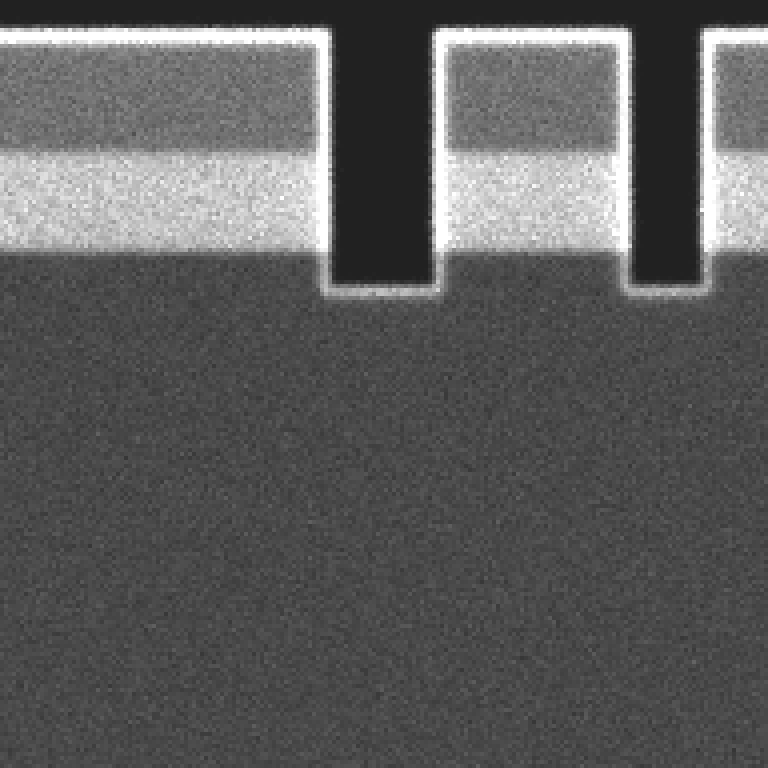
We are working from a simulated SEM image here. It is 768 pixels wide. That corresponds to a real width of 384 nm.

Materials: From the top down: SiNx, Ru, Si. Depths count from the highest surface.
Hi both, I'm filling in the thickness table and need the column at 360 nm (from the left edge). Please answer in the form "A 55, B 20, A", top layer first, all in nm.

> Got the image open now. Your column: SiNx 60, Ru 50, Si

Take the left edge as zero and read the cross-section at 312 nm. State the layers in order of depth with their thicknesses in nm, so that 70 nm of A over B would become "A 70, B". SiNx 60, Ru 50, Si